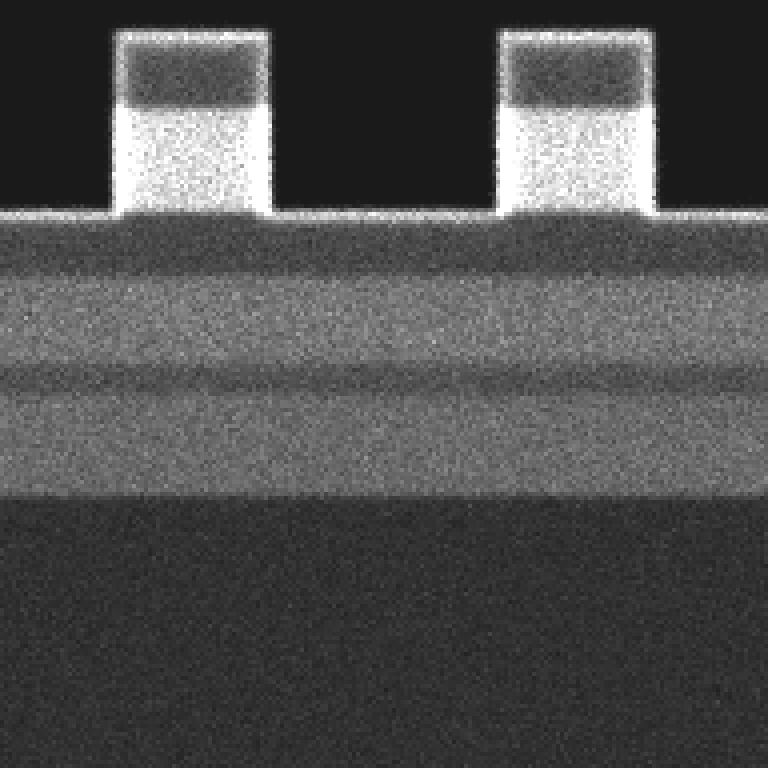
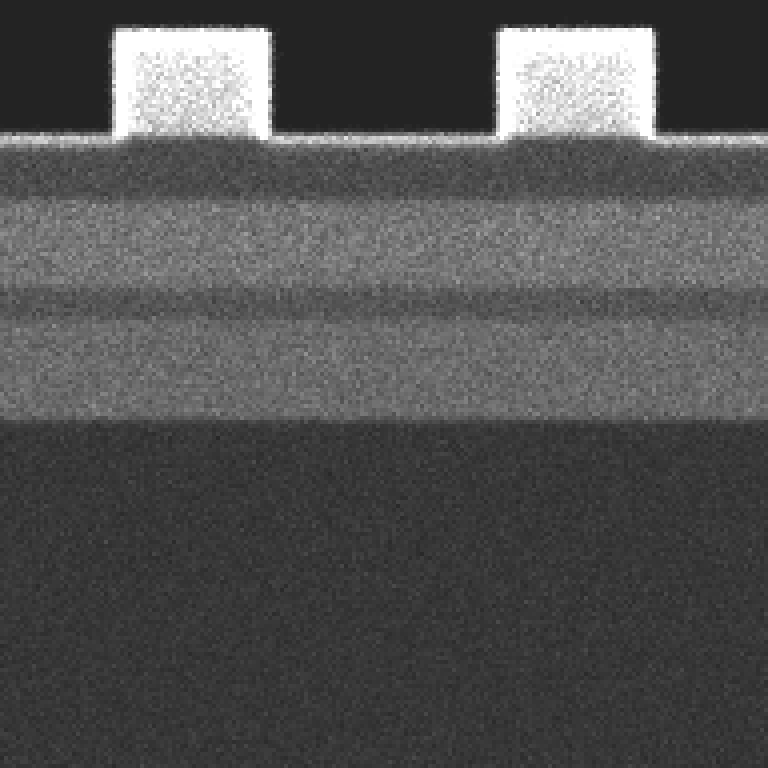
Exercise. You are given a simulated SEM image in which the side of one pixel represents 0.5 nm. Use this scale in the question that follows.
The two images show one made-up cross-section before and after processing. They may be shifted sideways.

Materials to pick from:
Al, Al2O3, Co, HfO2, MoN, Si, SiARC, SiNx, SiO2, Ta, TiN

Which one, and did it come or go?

SiARC - removed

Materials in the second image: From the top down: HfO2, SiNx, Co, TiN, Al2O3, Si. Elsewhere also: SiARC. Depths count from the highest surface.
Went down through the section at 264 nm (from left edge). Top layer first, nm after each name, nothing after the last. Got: HfO2 52, SiNx 32, Co 44, TiN 16, Al2O3 50, Si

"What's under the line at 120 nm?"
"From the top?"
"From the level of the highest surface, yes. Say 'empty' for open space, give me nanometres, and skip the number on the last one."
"HfO2 52, SiNx 32, Co 44, TiN 16, Al2O3 50, Si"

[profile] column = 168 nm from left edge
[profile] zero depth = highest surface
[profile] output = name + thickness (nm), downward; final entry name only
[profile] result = empty 52, SiNx 32, Co 44, TiN 16, Al2O3 50, Si